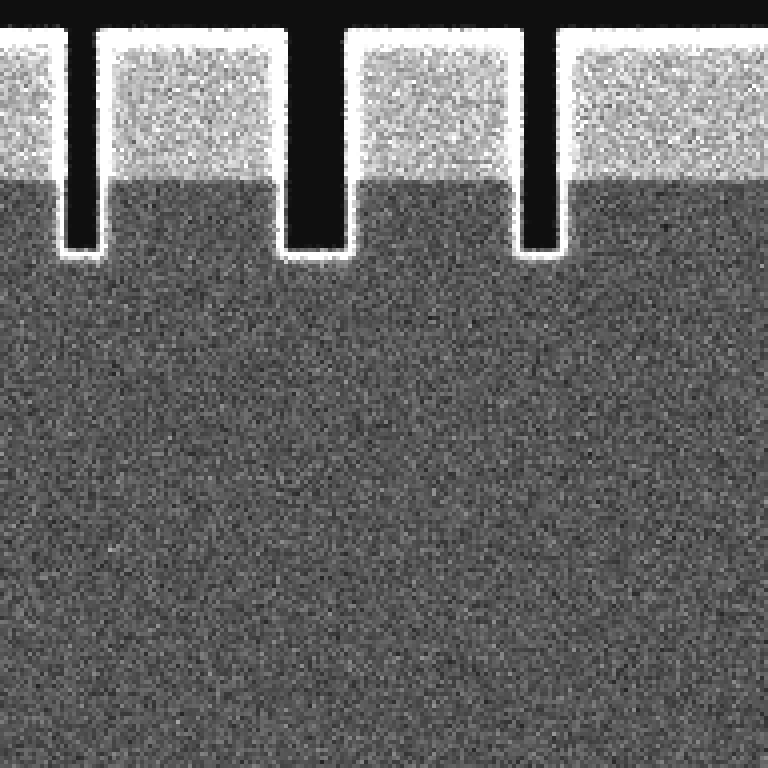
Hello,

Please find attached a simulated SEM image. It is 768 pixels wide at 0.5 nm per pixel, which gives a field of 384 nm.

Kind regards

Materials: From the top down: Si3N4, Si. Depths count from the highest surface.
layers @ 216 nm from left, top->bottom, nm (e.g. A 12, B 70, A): Si3N4 74, Si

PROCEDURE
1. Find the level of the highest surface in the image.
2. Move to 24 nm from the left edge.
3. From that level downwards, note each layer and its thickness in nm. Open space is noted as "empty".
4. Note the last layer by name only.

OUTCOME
Si3N4 74, Si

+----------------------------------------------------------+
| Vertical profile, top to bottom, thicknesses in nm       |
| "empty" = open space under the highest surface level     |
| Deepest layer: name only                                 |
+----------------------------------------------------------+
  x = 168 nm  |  empty 110, Si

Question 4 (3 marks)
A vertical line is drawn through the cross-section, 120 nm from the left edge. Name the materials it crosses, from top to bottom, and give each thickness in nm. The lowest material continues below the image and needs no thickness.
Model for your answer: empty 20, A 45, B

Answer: Si3N4 74, Si